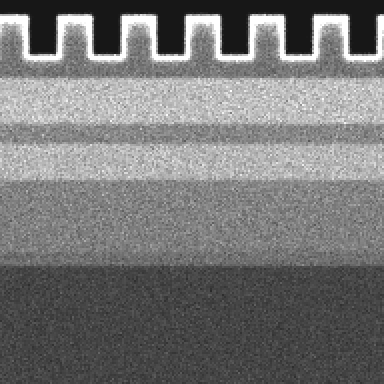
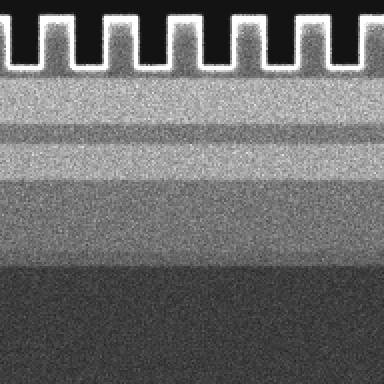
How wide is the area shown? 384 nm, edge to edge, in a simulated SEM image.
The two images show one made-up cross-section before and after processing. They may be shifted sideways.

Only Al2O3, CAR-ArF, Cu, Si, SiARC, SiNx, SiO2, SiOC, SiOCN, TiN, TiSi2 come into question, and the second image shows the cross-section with SiNx removed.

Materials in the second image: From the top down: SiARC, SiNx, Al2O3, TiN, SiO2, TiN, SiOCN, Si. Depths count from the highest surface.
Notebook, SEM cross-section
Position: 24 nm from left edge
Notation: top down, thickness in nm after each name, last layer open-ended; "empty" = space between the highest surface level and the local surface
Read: empty 50, SiNx 12, Al2O3 46, TiN 20, SiO2 36, TiN 72, SiOCN 14, Si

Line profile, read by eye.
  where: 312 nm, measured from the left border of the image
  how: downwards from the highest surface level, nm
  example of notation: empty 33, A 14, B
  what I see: SiARC 20, SiNx 42, Al2O3 46, TiN 20, SiO2 36, TiN 72, SiOCN 14, Si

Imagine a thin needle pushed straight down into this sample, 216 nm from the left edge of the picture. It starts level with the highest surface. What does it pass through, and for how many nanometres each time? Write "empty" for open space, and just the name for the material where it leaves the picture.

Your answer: empty 50, SiNx 12, Al2O3 46, TiN 20, SiO2 36, TiN 72, SiOCN 14, Si